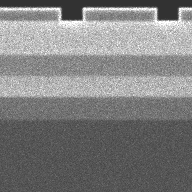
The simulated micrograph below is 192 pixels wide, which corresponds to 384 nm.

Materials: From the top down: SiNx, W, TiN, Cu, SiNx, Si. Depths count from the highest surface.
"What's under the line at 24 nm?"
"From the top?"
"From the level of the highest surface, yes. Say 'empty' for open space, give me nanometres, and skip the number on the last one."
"SiNx 26, W 68, TiN 42, Cu 42, SiNx 46, Si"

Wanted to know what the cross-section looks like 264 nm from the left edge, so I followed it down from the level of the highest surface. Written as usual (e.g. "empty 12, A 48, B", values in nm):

SiNx 26, W 68, TiN 42, Cu 42, SiNx 46, Si